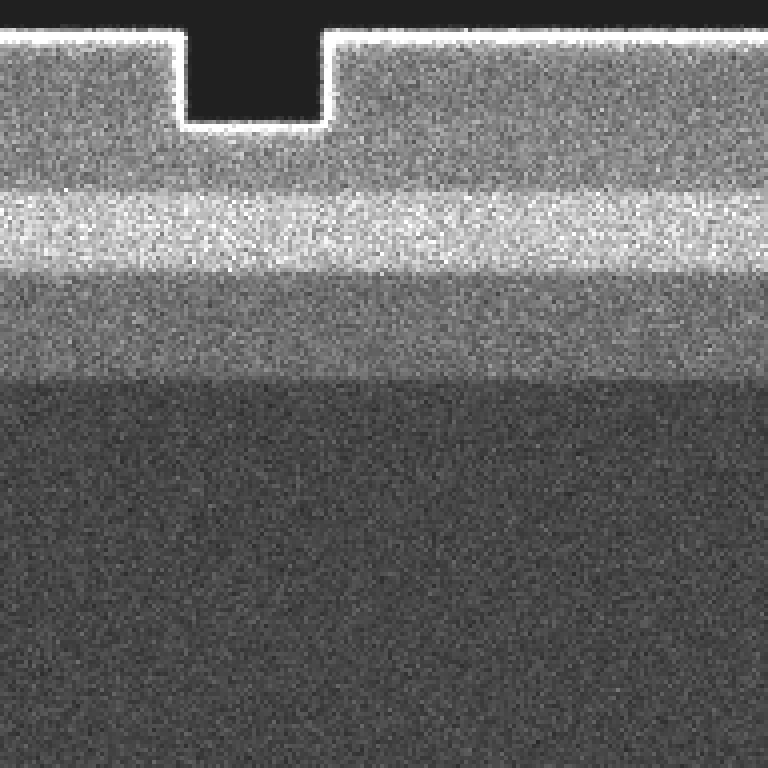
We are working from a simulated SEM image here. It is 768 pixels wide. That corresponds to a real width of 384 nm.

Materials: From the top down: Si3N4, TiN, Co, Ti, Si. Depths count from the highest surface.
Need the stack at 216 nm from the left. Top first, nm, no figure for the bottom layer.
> Si3N4 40, TiN 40, Co 40, Ti 54, Si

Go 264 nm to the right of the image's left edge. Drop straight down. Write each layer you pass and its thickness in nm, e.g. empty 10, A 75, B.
Si3N4 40, TiN 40, Co 40, Ti 54, Si